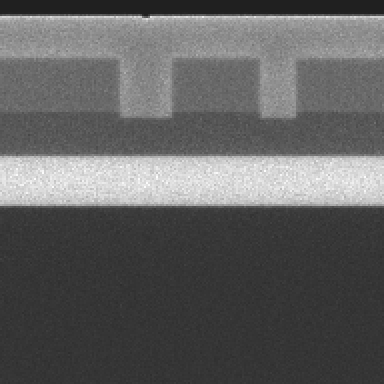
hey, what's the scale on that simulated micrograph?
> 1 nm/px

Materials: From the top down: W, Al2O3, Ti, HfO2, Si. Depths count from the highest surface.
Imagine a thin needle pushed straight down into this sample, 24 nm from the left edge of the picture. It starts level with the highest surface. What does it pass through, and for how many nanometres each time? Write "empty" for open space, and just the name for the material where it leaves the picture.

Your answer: W 42, Al2O3 54, Ti 44, HfO2 50, Si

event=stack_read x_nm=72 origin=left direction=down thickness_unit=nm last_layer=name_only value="W 42, Al2O3 54, Ti 44, HfO2 50, Si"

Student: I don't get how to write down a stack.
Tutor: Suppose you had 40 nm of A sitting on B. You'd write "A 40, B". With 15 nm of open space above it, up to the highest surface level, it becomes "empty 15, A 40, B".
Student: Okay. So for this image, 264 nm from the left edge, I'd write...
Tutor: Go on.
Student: W 102, Ti 38, HfO2 50, Si